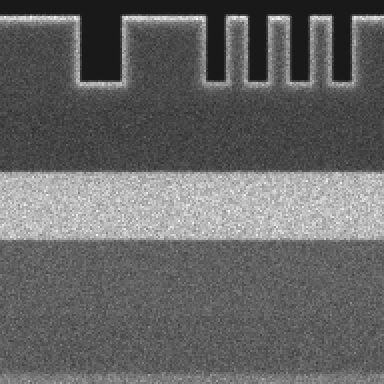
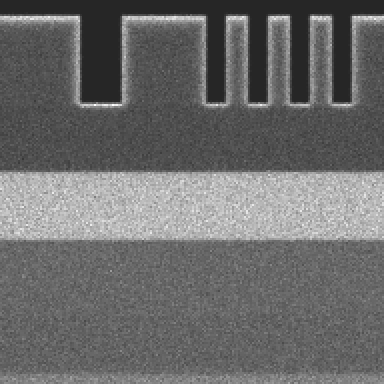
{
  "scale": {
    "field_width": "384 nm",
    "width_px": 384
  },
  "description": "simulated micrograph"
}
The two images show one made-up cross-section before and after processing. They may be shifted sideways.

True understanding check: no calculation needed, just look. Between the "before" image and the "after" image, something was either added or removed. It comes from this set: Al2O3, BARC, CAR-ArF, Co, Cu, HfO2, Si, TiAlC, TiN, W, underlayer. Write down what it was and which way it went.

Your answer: underlayer (removed)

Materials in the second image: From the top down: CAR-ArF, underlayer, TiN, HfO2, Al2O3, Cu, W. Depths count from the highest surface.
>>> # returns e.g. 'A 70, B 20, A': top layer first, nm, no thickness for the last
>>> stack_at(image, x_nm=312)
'CAR-ArF 66, underlayer 22, TiN 68, HfO2 68, Al2O3 76, Cu 58, W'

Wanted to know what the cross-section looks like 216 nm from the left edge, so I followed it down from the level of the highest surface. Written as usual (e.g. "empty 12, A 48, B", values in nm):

empty 88, TiN 68, HfO2 68, Al2O3 76, Cu 58, W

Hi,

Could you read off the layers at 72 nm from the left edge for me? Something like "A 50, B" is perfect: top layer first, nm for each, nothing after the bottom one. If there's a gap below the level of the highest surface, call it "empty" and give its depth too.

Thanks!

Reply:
CAR-ArF 66, underlayer 22, TiN 68, HfO2 68, Al2O3 76, Cu 58, W